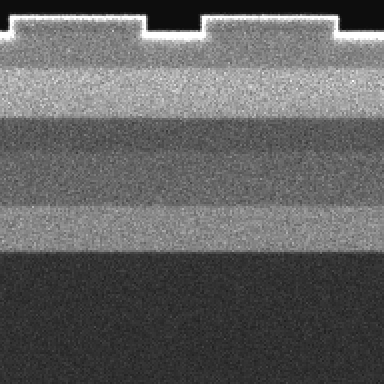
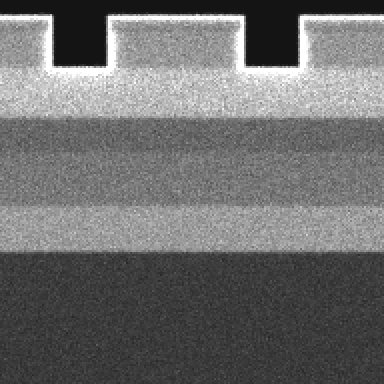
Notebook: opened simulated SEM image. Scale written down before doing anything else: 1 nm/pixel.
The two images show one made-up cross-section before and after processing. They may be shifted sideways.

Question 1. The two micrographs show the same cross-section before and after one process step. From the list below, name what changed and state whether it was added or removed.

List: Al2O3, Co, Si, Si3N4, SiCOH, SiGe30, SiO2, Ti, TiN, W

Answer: SiO2, removed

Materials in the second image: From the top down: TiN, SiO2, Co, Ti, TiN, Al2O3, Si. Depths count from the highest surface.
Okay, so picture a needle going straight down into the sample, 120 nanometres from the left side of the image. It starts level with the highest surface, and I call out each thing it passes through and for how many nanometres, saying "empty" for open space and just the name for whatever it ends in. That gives TiN 16, SiO2 36, Co 50, Ti 34, TiN 54, Al2O3 46, Si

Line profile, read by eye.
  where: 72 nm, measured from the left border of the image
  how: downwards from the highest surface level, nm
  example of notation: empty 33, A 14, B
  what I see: empty 52, Co 50, Ti 34, TiN 54, Al2O3 46, Si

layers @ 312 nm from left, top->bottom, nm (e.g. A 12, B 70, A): TiN 16, SiO2 36, Co 50, Ti 34, TiN 54, Al2O3 46, Si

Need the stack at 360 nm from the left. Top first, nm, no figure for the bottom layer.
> TiN 16, SiO2 36, Co 50, Ti 34, TiN 54, Al2O3 46, Si